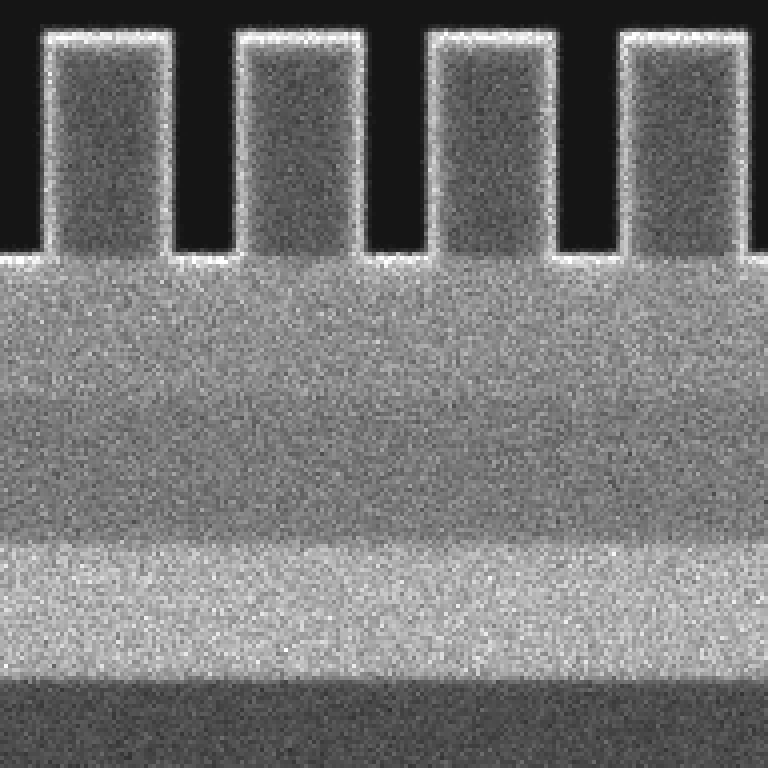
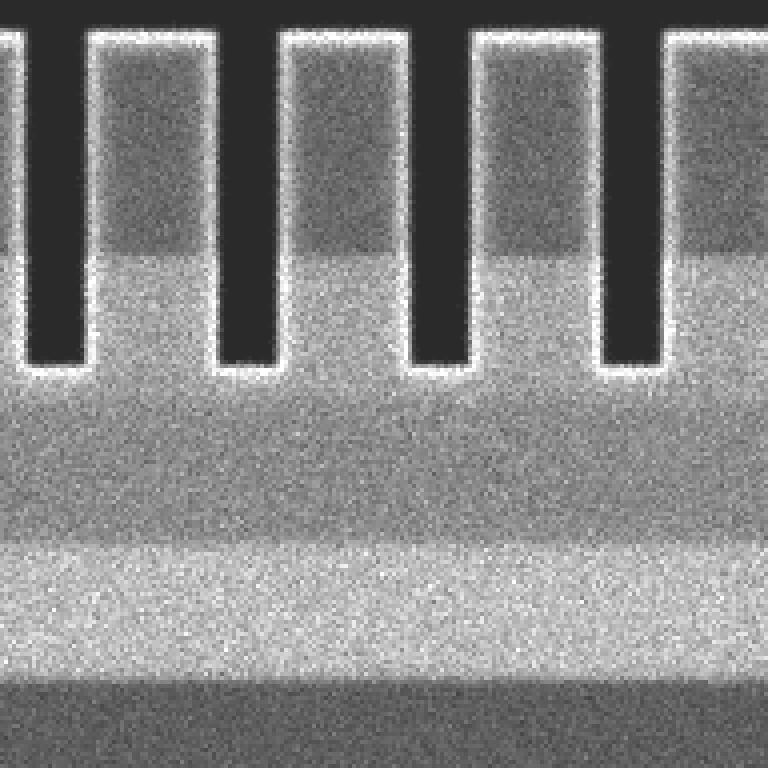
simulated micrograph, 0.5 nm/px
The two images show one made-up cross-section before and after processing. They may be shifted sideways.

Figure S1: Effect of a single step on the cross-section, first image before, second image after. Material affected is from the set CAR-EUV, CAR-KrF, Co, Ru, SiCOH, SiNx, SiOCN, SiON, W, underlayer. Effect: removed Ru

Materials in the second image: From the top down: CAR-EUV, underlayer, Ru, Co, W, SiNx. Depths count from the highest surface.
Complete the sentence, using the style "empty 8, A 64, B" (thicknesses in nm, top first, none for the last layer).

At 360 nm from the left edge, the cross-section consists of CAR-EUV 64, underlayer 48, Ru 72, Co 72, W 68, SiNx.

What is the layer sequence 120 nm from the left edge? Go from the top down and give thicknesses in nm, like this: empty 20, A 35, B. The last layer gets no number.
empty 168, Ru 16, Co 72, W 68, SiNx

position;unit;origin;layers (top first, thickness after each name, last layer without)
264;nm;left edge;CAR-EUV 64, underlayer 48, Ru 72, Co 72, W 68, SiNx